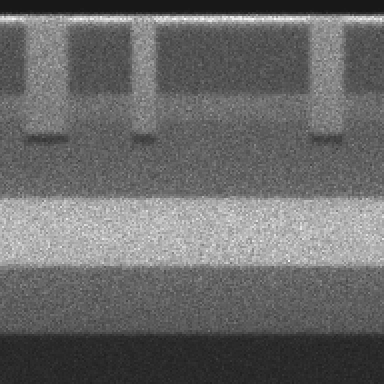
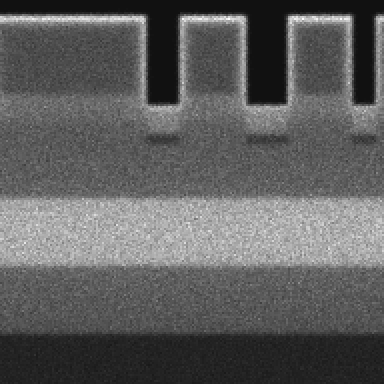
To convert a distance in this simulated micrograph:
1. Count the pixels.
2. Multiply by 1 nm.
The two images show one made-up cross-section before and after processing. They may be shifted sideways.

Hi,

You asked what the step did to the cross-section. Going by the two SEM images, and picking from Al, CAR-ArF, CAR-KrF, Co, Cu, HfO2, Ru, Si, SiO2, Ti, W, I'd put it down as W, removed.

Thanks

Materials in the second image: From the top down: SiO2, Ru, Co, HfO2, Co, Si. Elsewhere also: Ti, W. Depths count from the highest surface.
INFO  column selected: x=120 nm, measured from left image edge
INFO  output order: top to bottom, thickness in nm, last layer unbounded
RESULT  SiO2 78, Ru 26, Co 78, HfO2 68, Co 68, Si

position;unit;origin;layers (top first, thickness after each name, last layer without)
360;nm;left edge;empty 90, W 28, Ti 10, Co 54, HfO2 68, Co 68, Si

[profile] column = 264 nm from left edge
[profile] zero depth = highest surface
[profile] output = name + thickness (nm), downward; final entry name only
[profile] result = empty 90, W 28, Ti 10, Co 54, HfO2 68, Co 68, Si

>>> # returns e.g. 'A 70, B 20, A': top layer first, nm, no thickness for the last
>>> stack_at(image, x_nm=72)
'SiO2 78, Ru 26, Co 78, HfO2 68, Co 68, Si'